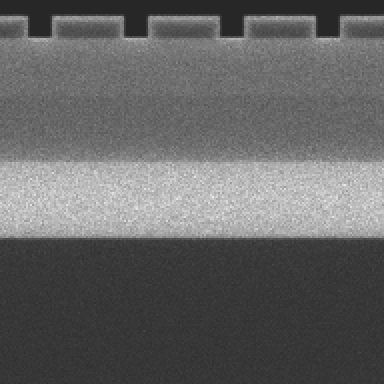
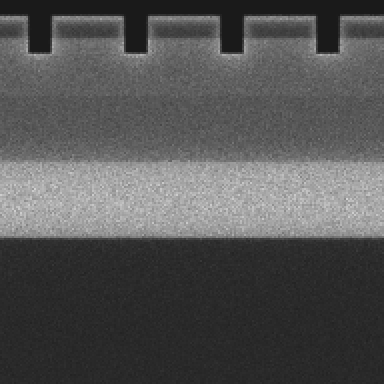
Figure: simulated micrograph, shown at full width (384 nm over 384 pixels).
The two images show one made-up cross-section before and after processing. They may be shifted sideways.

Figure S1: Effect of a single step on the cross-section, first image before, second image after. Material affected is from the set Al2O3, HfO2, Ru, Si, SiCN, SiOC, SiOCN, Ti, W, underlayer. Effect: removed W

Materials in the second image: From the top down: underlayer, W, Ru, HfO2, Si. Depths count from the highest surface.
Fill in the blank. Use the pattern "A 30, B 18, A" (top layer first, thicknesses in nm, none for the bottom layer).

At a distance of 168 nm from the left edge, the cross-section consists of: underlayer 22, W 58, Ru 66, HfO2 76, Si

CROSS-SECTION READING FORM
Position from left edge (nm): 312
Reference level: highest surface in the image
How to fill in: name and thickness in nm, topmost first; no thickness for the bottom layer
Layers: underlayer 22, W 58, Ru 66, HfO2 76, Si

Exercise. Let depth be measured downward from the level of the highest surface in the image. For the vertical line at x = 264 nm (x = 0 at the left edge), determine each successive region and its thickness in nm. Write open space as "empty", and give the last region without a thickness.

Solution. underlayer 22, W 58, Ru 66, HfO2 76, Si